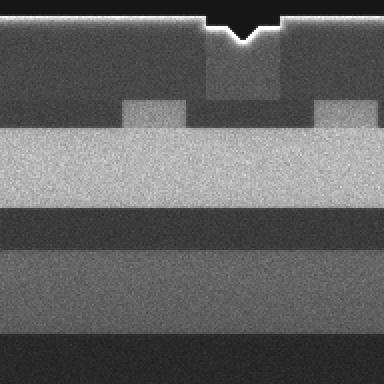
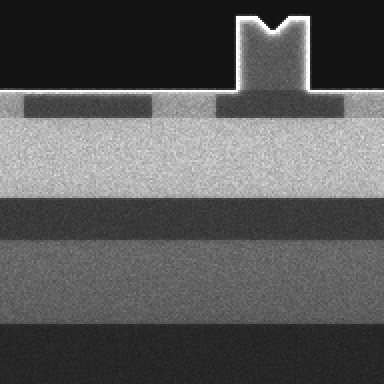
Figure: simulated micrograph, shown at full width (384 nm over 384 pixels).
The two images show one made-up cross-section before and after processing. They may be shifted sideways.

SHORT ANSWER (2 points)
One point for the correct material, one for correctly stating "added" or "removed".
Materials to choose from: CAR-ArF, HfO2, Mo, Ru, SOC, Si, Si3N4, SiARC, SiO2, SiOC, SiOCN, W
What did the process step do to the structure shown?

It removed SOC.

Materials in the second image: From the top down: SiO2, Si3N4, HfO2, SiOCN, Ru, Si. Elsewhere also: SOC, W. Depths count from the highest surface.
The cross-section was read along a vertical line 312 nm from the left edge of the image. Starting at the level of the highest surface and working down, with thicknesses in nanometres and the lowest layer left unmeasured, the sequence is empty 74, Si3N4 28, HfO2 80, SiOCN 42, Ru 84, Si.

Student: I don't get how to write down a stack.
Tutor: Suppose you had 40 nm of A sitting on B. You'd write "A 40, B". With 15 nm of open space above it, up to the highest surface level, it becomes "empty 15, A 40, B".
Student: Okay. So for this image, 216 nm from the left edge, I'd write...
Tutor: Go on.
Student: empty 74, Si3N4 28, HfO2 80, SiOCN 42, Ru 84, Si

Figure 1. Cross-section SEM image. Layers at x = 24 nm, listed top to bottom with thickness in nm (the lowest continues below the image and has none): empty 74, Si3N4 28, HfO2 80, SiOCN 42, Ru 84, Si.